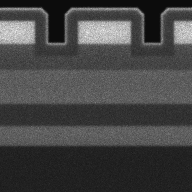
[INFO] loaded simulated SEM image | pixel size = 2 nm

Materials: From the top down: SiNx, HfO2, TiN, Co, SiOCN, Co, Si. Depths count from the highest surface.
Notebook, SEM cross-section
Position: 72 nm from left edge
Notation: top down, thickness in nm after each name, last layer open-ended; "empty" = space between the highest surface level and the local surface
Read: SiNx 96, TiN 28, Co 68, SiOCN 44, Co 40, Si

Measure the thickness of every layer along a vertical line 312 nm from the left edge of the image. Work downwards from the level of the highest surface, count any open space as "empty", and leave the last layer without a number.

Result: empty 70, SiNx 26, TiN 28, Co 68, SiOCN 44, Co 40, Si